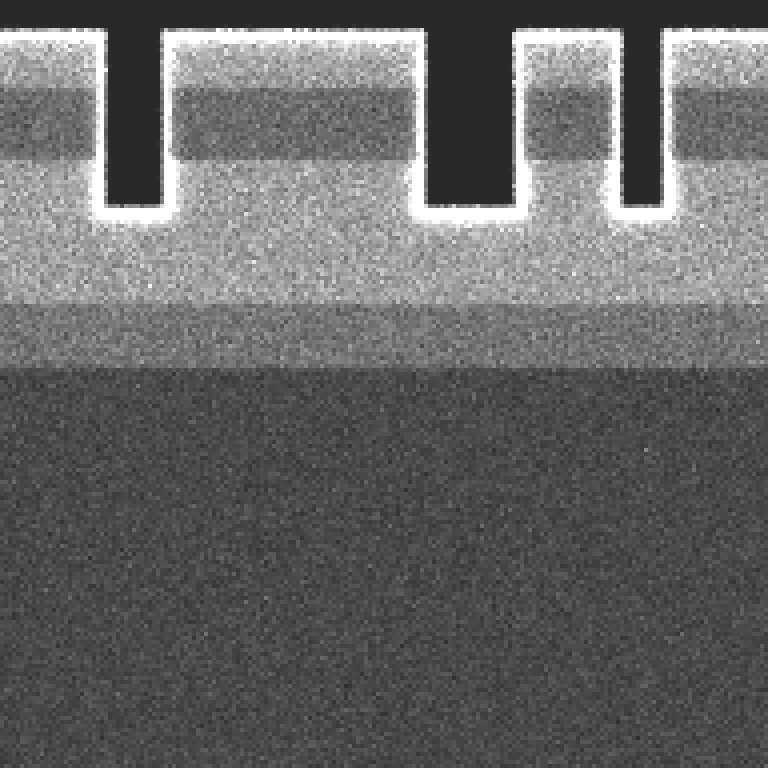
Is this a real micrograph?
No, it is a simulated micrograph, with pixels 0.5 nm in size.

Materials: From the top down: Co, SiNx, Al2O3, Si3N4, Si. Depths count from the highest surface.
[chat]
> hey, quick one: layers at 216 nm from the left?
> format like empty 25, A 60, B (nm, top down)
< empty 88, Al2O3 48, Si3N4 32, Si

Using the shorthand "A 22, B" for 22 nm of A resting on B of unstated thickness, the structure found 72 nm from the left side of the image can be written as empty 88, Al2O3 48, Si3N4 32, Si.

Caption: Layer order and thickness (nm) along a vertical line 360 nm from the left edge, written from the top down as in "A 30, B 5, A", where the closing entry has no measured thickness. Co 28, SiNx 36, Al2O3 72, Si3N4 32, Si